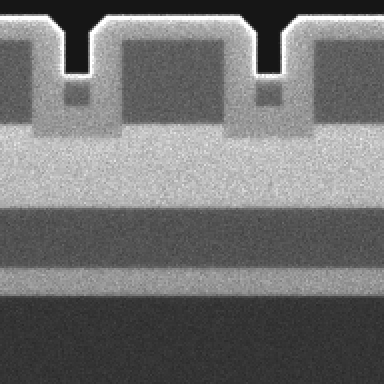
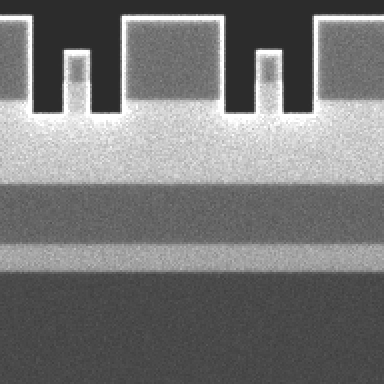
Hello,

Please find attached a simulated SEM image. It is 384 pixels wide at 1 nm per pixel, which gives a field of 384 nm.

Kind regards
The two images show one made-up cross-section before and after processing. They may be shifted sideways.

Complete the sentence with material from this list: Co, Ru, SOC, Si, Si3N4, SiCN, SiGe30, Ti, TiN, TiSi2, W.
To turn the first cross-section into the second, Co must be removed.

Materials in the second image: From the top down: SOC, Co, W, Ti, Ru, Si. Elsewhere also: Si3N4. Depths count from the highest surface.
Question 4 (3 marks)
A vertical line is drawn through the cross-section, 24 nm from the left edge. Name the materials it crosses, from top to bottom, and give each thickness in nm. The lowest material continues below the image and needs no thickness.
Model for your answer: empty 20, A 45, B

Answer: Si3N4 84, W 84, Ti 60, Ru 28, Si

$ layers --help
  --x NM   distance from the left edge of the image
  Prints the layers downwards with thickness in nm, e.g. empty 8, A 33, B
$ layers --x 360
Si3N4 84, W 84, Ti 60, Ru 28, Si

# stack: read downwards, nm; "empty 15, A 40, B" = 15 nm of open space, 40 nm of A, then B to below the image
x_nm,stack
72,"empty 34, SOC 32, Co 32, W 70, Ti 60, Ru 28, Si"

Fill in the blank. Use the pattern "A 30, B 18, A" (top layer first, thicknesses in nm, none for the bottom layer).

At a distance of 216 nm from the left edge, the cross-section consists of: Si3N4 84, W 84, Ti 60, Ru 28, Si